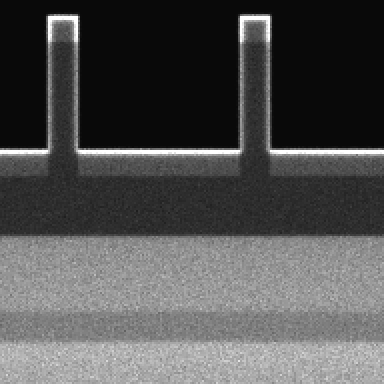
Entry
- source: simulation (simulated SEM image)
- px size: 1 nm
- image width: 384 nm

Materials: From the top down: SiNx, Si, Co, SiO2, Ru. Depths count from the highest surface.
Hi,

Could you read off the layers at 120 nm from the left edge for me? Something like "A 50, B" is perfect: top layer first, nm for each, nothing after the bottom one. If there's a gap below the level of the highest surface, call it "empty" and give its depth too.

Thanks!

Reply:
empty 134, SiNx 26, Si 60, Co 76, SiO2 30, Ru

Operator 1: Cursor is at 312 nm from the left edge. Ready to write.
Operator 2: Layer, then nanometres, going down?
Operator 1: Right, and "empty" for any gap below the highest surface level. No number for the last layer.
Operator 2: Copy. empty 134, SiNx 26, Si 60, Co 76, SiO2 30, Ru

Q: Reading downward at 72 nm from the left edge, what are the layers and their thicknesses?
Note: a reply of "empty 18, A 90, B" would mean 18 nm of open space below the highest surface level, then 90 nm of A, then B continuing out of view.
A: SiNx 26, Si 194, Co 76, SiO2 30, Ru